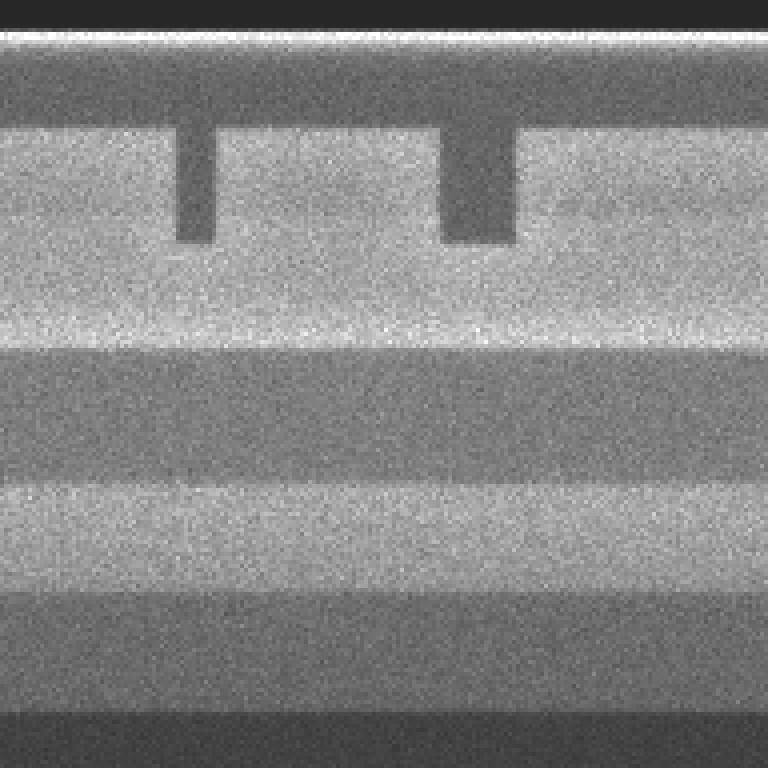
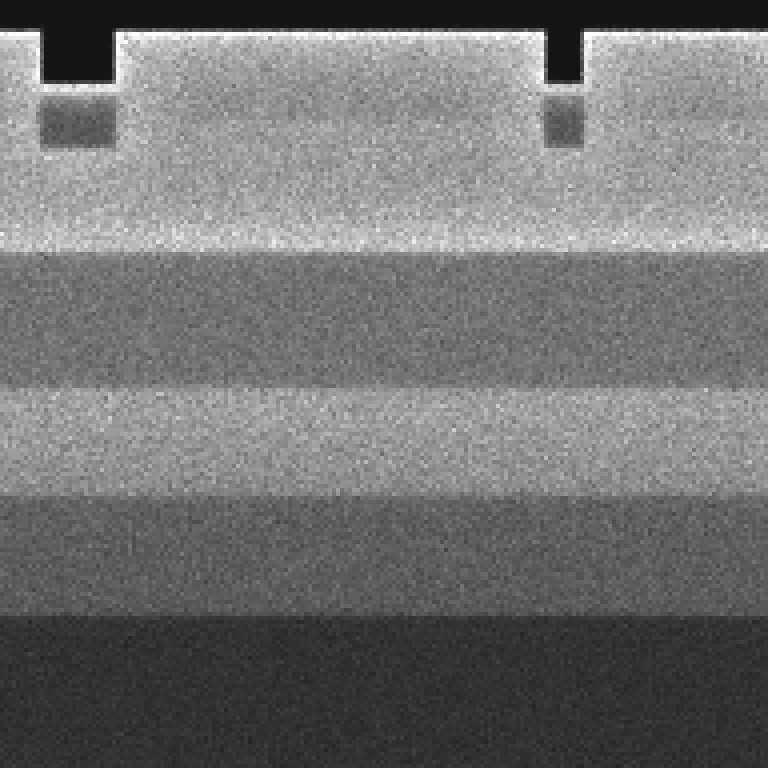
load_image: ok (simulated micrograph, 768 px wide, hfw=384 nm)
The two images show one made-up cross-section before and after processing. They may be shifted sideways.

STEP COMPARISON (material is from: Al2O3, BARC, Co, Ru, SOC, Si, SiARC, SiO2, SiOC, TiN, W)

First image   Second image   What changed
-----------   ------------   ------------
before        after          SOC, removed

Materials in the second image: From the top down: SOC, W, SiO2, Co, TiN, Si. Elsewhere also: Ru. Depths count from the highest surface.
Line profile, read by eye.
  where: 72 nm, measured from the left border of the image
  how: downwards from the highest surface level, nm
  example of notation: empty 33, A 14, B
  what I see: Ru 44, W 66, SiO2 68, Co 54, TiN 60, Si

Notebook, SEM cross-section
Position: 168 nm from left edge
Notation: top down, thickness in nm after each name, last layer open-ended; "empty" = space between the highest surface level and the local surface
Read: Ru 44, W 66, SiO2 68, Co 54, TiN 60, Si